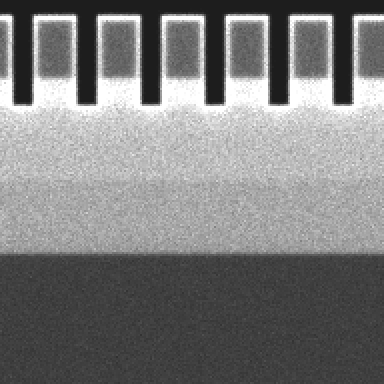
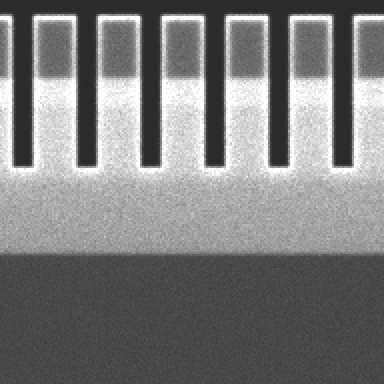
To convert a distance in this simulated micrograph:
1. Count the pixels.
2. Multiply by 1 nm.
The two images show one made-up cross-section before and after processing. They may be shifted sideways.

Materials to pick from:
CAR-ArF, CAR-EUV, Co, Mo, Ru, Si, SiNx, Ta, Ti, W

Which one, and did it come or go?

Ru - removed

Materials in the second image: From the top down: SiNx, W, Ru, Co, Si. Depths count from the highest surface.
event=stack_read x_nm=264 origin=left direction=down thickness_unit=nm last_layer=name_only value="SiNx 62, W 28, Ru 74, Co 74, Si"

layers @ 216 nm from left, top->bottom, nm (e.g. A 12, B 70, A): empty 152, Ru 12, Co 74, Si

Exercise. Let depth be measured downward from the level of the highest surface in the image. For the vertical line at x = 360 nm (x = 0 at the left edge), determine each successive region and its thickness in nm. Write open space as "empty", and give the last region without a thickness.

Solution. SiNx 62, W 28, Ru 74, Co 74, Si